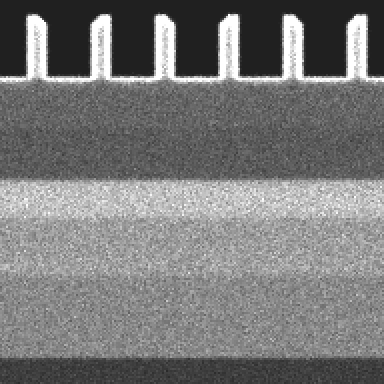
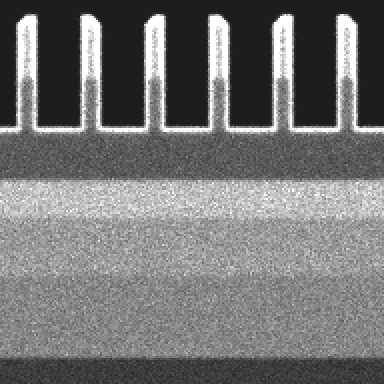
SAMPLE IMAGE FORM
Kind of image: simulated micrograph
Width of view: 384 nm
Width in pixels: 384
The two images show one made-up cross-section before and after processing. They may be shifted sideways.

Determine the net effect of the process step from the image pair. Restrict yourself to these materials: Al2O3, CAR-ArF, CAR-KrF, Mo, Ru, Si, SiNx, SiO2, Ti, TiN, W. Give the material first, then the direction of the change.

TiN: removed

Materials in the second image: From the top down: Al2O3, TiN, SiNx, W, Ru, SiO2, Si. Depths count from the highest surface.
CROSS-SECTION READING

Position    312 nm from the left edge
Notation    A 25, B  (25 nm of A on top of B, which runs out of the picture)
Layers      empty 112, SiNx 52, W 38, Ru 58, SiO2 82, Si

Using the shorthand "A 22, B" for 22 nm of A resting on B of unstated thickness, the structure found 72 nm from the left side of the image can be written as empty 112, SiNx 52, W 38, Ru 58, SiO2 82, Si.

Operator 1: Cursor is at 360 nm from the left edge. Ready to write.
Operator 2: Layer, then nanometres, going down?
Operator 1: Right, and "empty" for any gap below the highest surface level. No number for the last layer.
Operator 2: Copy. empty 112, SiNx 52, W 38, Ru 58, SiO2 82, Si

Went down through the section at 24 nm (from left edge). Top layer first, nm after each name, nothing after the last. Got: empty 2, Al2O3 60, TiN 50, SiNx 52, W 38, Ru 58, SiO2 82, Si